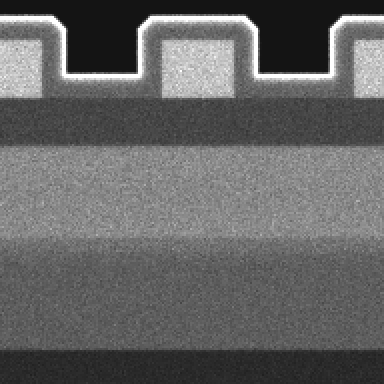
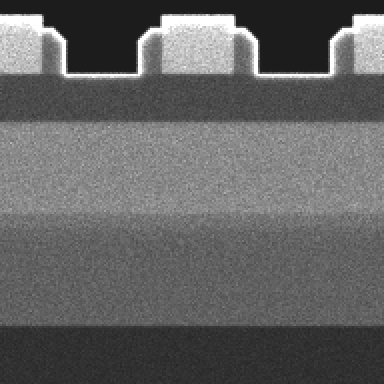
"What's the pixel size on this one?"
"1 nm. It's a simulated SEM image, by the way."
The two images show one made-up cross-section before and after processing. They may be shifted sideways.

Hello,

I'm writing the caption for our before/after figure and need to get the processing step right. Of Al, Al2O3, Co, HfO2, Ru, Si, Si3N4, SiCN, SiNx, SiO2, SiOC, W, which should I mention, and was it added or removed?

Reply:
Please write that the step removed Al2O3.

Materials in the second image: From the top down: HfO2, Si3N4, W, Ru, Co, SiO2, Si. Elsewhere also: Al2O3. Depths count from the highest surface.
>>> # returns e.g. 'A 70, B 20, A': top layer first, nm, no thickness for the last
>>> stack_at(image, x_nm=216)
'HfO2 58, Si3N4 48, W 92, Ru 14, Co 12, SiO2 86, Si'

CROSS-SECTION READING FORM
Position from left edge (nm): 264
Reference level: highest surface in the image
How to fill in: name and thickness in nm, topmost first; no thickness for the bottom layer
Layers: empty 58, Si3N4 48, W 92, Ru 14, Co 12, SiO2 86, Si